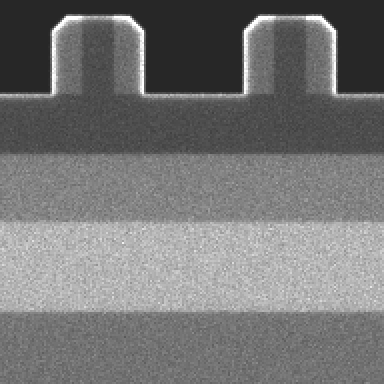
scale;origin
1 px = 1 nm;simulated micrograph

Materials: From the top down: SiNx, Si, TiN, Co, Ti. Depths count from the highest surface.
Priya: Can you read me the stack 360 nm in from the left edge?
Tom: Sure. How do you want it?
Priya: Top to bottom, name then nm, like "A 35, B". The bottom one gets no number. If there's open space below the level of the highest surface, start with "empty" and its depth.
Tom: empty 78, Si 60, TiN 68, Co 90, Ti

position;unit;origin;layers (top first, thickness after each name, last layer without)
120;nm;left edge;SiNx 78, Si 60, TiN 68, Co 90, Ti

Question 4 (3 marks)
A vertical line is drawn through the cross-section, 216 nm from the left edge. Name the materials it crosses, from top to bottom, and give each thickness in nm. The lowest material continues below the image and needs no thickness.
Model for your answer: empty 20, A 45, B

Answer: empty 78, Si 60, TiN 68, Co 90, Ti